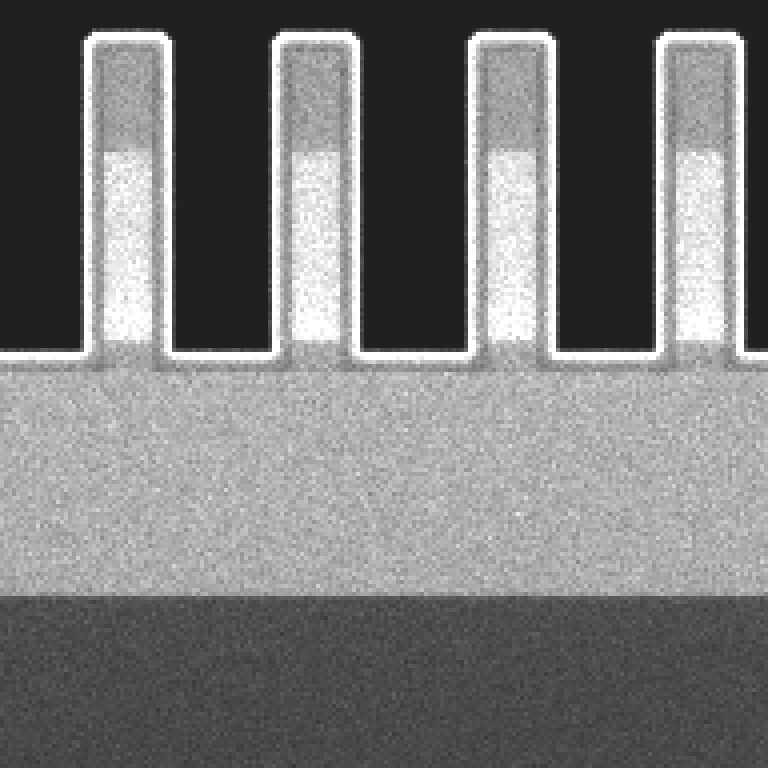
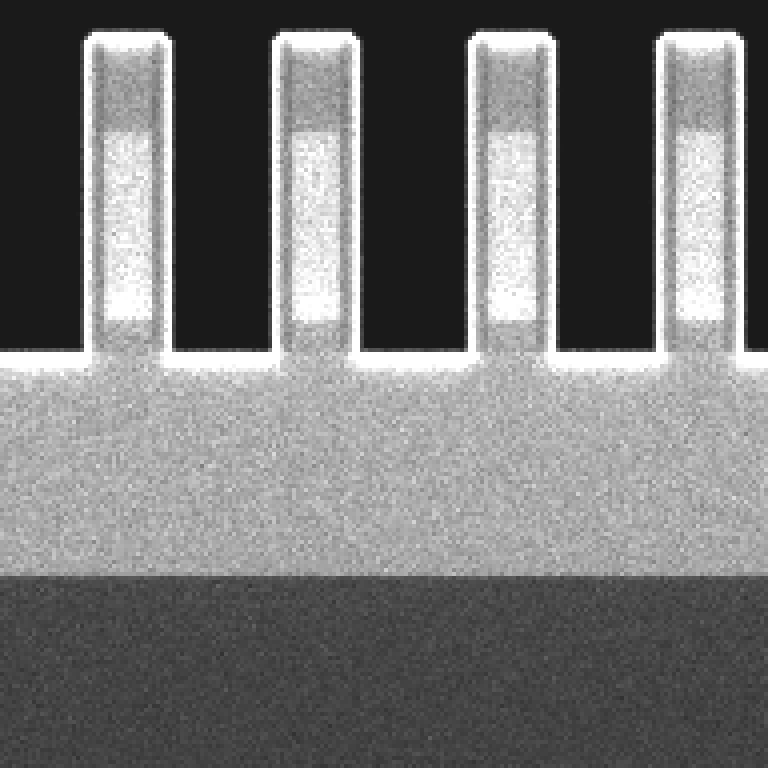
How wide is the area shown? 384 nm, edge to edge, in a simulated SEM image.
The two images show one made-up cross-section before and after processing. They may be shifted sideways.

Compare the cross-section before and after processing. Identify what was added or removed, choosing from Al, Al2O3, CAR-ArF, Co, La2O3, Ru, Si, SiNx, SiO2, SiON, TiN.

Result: SiNx removed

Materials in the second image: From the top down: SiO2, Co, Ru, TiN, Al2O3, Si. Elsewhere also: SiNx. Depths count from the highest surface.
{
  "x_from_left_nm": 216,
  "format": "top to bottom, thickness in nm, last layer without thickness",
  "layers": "empty 160, Al2O3 112, Si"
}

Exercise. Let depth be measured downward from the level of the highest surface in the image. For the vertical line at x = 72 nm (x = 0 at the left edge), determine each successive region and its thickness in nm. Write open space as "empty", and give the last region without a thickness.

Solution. SiO2 50, Co 80, Ru 14, TiN 16, Al2O3 112, Si